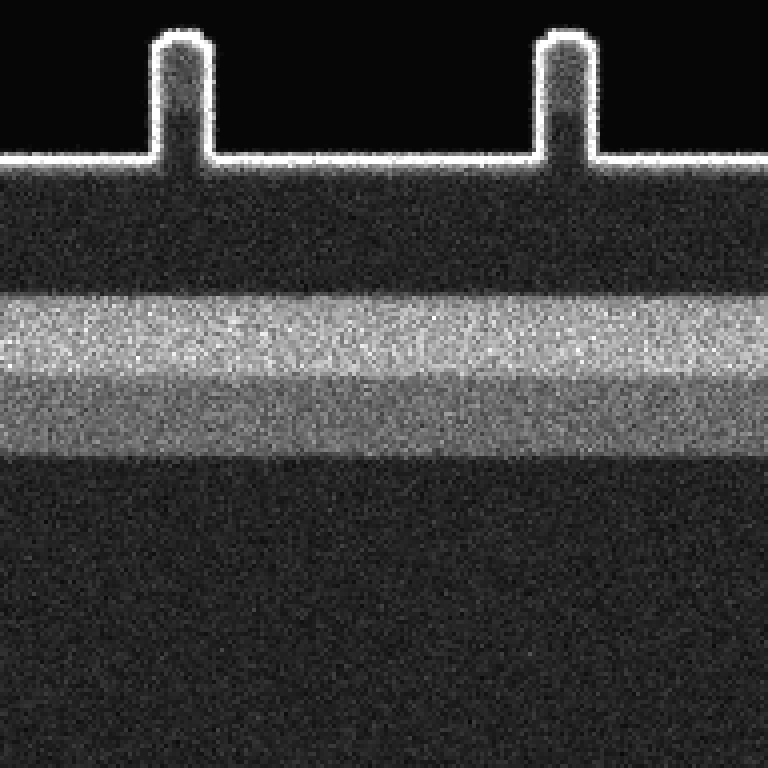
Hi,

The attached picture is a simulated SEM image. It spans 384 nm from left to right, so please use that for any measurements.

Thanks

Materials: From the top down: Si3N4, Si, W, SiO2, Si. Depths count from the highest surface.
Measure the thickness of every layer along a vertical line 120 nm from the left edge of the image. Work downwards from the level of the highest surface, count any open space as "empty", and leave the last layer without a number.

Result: empty 62, Si3N4 10, Si 60, W 40, SiO2 40, Si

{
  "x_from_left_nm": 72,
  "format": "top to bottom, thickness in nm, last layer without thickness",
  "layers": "empty 62, Si3N4 10, Si 60, W 40, SiO2 40, Si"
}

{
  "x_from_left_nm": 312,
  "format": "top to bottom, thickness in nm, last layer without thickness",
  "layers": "empty 62, Si3N4 10, Si 60, W 40, SiO2 40, Si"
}